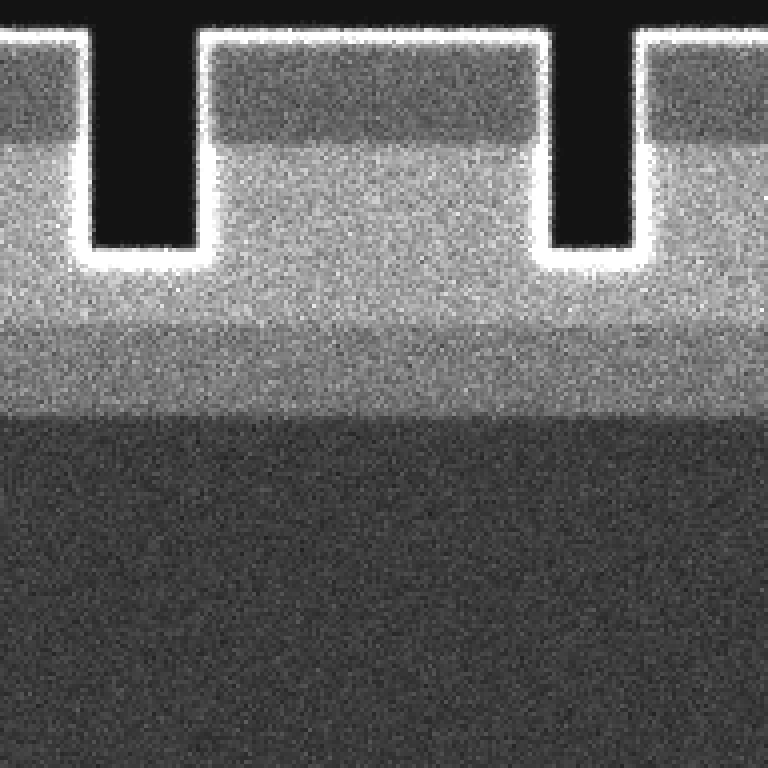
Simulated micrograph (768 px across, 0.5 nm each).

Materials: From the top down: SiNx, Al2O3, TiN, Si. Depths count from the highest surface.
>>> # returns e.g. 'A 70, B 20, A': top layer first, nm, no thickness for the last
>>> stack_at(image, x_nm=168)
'SiNx 56, Al2O3 90, TiN 46, Si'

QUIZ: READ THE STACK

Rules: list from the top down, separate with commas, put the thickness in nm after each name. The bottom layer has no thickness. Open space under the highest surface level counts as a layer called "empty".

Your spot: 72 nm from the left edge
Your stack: empty 110, Al2O3 36, TiN 46, Si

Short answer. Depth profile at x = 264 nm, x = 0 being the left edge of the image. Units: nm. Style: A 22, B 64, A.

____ SiNx 56, Al2O3 90, TiN 46, Si